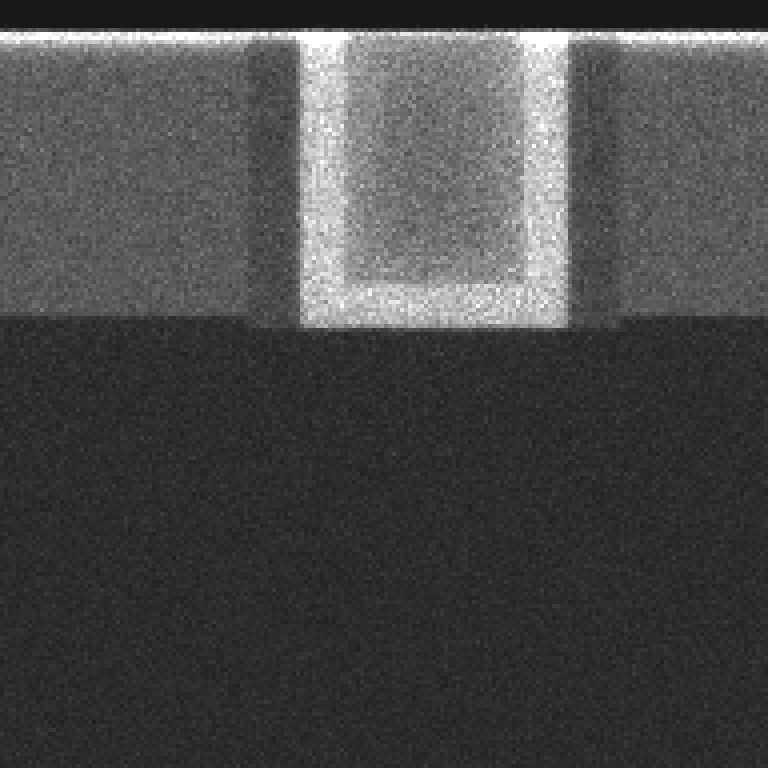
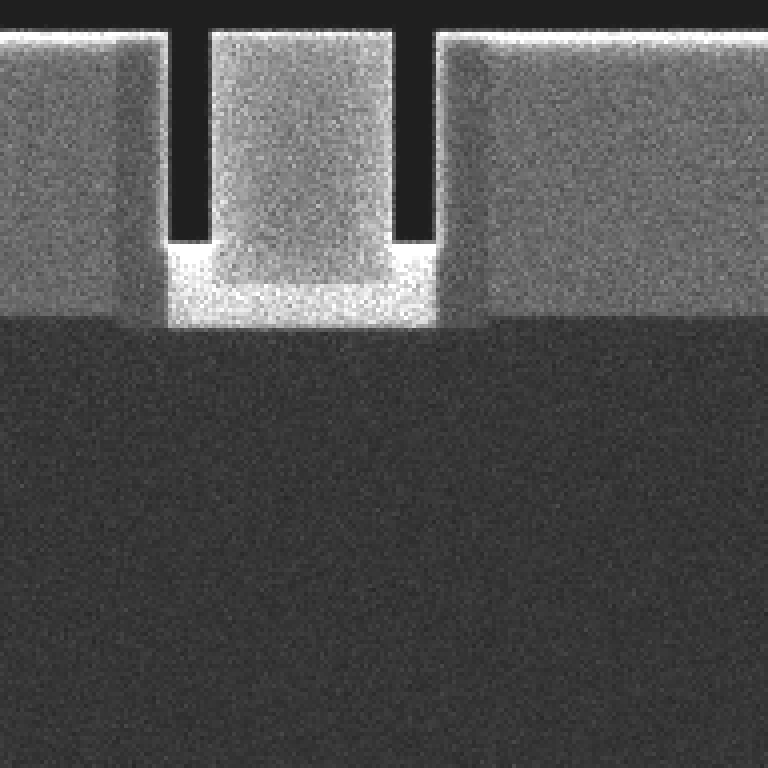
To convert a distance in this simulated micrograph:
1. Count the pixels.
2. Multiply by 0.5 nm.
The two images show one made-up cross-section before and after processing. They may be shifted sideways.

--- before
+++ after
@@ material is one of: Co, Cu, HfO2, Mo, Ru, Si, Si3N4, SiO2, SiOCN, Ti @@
HfO2 removed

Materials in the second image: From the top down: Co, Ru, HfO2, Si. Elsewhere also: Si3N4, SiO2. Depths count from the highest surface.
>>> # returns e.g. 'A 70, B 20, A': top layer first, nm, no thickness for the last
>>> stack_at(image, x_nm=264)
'SiO2 142, Si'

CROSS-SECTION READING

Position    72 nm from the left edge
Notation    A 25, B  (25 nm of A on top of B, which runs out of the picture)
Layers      Si3N4 148, Si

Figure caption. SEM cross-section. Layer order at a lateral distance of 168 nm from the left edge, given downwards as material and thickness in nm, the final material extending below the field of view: Co 108, Ru 18, HfO2 22, Si